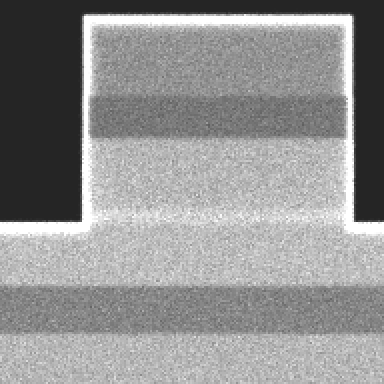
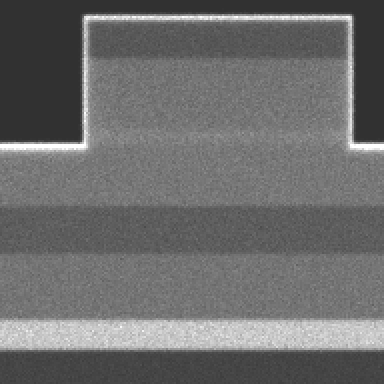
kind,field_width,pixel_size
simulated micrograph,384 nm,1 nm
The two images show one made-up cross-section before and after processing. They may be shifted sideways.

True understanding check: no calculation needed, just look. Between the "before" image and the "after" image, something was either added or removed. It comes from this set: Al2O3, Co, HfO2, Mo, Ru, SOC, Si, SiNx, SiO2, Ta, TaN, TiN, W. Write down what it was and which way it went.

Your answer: SOC (removed)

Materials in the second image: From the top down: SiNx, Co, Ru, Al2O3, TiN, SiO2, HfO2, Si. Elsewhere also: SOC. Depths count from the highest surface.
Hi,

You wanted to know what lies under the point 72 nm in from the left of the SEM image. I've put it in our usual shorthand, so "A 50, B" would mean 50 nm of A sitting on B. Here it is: empty 128, Al2O3 62, TiN 48, SiO2 66, HfO2 30, Si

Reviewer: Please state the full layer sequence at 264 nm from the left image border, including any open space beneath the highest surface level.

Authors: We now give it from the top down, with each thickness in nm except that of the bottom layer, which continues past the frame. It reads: SiNx 42, Co 72, Ru 14, Al2O3 62, TiN 48, SiO2 66, HfO2 30, Si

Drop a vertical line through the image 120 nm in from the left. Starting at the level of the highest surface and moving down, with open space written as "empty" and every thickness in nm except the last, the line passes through SiNx 42, Co 72, Ru 14, Al2O3 62, TiN 48, SiO2 66, HfO2 30, Si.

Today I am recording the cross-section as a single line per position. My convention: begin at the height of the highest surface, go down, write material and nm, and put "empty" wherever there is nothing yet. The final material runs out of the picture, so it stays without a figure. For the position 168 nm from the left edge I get SiNx 42, Co 72, Ru 14, Al2O3 62, TiN 48, SiO2 66, HfO2 30, Si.